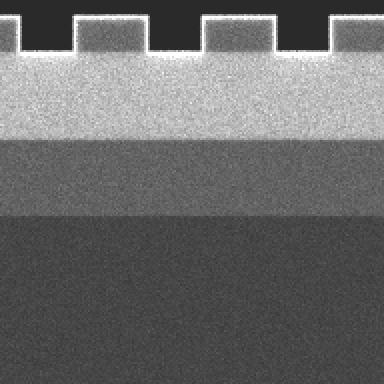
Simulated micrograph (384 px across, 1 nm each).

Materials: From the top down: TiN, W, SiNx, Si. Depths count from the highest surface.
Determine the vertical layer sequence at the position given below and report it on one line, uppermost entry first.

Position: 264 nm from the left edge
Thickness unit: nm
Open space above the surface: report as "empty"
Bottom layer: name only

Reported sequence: TiN 36, W 88, SiNx 76, Si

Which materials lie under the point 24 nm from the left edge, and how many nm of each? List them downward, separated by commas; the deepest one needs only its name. empty 36, W 88, SiNx 76, Si